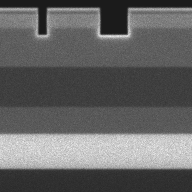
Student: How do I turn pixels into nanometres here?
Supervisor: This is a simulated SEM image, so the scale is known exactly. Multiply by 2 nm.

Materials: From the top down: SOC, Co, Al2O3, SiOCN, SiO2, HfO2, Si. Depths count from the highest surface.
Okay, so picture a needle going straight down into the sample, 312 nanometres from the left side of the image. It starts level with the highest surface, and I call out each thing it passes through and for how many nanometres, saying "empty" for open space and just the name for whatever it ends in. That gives SOC 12, Co 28, Al2O3 78, SiOCN 80, SiO2 54, HfO2 70, Si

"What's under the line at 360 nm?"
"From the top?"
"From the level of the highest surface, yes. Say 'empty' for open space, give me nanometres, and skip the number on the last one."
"SOC 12, Co 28, Al2O3 78, SiOCN 80, SiO2 54, HfO2 70, Si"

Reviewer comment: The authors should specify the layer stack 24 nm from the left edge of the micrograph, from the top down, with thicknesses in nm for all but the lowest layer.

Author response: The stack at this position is SOC 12, Co 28, Al2O3 78, SiOCN 80, SiO2 54, HfO2 70, Si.